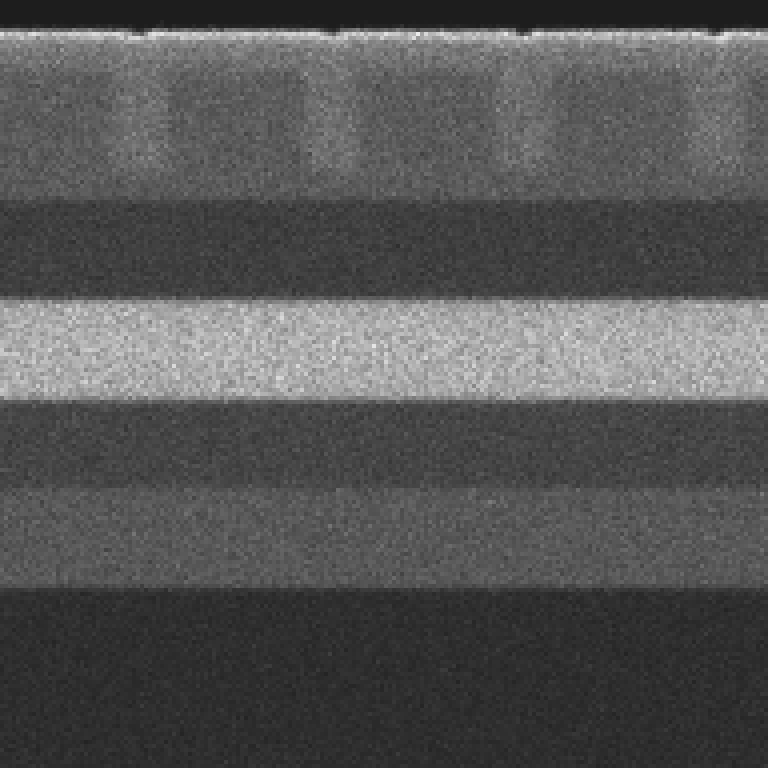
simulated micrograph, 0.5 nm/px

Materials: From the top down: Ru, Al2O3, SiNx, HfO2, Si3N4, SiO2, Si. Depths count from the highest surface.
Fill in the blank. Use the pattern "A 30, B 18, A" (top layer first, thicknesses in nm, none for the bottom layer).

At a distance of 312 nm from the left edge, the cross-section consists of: Ru 20, Al2O3 64, SiNx 50, HfO2 50, Si3N4 44, SiO2 50, Si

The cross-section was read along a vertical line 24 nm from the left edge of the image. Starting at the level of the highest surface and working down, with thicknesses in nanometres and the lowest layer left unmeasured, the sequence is Ru 20, Al2O3 64, SiNx 50, HfO2 50, Si3N4 44, SiO2 50, Si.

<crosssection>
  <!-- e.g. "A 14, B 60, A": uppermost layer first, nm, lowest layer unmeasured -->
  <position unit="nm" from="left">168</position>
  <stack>empty 2, Ru 68, Al2O3 14, SiNx 50, HfO2 50, Si3N4 44, SiO2 50, Si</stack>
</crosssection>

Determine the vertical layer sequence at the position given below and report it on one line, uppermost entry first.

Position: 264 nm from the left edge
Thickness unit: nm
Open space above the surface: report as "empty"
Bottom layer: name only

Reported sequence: empty 2, Ru 68, Al2O3 14, SiNx 50, HfO2 50, Si3N4 44, SiO2 50, Si